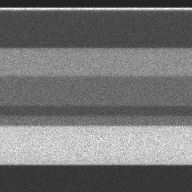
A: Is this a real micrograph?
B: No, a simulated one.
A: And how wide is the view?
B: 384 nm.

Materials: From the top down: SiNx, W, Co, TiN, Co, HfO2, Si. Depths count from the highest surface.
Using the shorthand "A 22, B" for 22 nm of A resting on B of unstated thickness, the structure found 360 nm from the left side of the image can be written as SiNx 80, W 56, Co 60, TiN 20, Co 20, HfO2 78, Si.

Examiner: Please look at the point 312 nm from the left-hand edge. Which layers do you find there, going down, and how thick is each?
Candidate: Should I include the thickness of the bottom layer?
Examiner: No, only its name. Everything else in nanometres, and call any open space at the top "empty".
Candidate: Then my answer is SiNx 80, W 56, Co 60, TiN 20, Co 20, HfO2 78, Si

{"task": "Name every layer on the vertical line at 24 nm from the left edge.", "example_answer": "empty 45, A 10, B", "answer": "SiNx 80, W 56, Co 60, TiN 20, Co 20, HfO2 78, Si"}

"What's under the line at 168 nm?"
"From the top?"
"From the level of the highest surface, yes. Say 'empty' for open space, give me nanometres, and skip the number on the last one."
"SiNx 80, W 56, Co 60, TiN 20, Co 20, HfO2 78, Si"